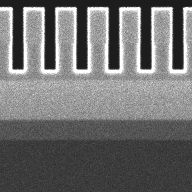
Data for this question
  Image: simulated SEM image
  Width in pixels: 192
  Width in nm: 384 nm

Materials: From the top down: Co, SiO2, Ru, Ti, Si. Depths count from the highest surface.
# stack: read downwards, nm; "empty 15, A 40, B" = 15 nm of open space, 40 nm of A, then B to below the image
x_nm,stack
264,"Co 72, SiO2 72, Ru 80, Ti 40, Si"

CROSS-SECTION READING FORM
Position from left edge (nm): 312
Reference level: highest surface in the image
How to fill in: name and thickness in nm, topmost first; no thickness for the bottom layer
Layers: Co 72, SiO2 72, Ru 80, Ti 40, Si